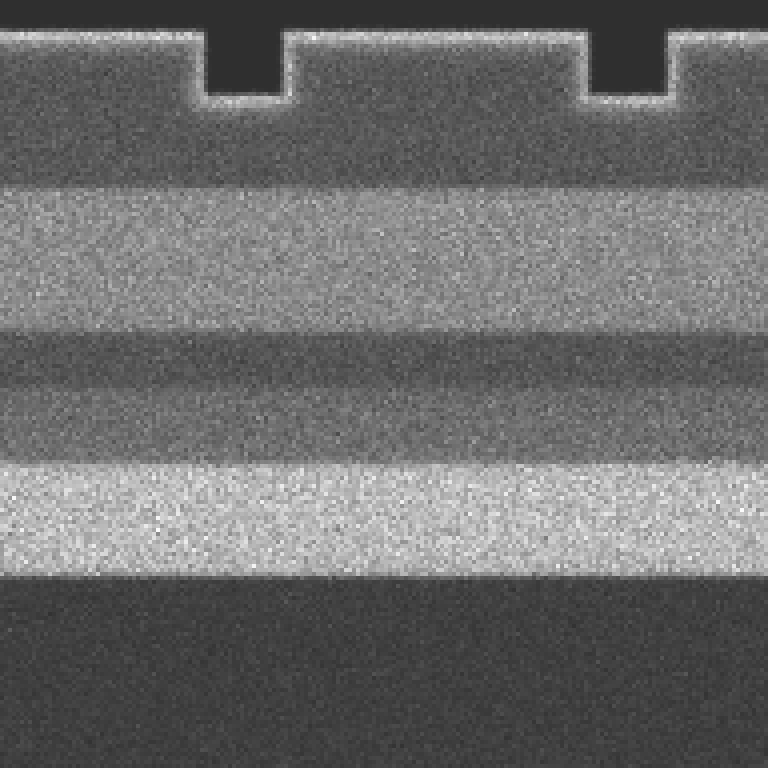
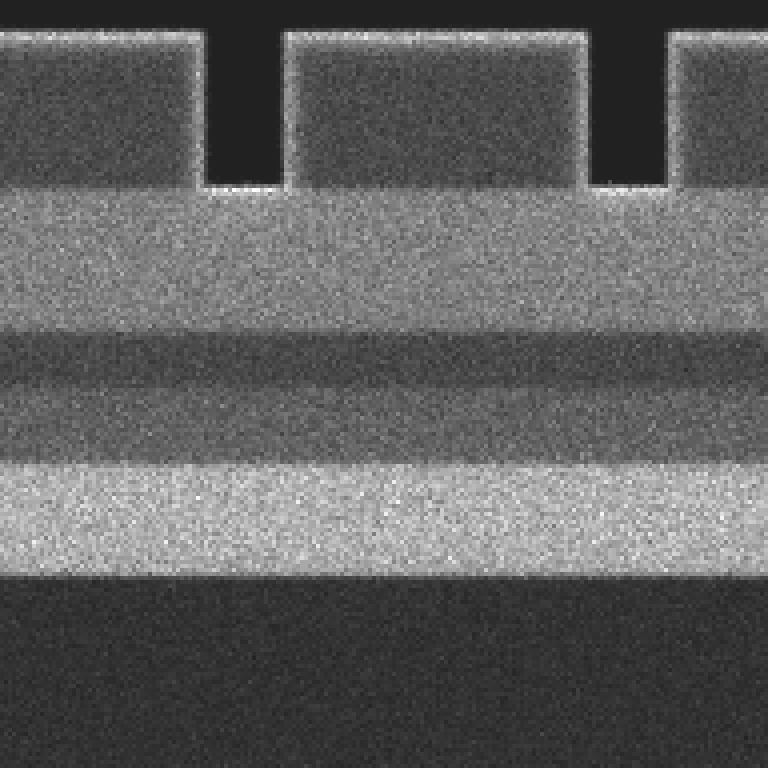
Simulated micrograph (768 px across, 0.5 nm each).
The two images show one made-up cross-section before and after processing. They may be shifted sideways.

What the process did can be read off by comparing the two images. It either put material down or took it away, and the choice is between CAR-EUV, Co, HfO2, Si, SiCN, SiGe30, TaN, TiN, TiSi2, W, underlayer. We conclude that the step removed underlayer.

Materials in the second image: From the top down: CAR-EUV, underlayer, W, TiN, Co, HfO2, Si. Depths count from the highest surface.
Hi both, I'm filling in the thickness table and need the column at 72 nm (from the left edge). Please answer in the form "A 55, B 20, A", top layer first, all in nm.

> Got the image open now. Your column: CAR-EUV 32, underlayer 46, W 72, TiN 28, Co 38, HfO2 56, Si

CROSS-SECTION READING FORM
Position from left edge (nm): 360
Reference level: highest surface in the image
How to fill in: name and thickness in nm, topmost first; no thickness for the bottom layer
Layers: CAR-EUV 32, underlayer 46, W 72, TiN 28, Co 38, HfO2 56, Si